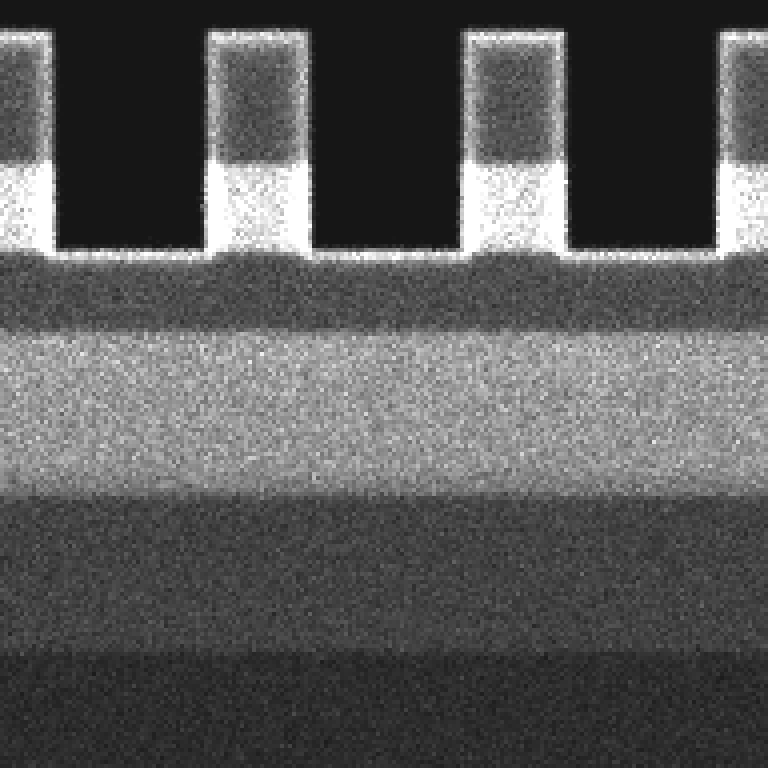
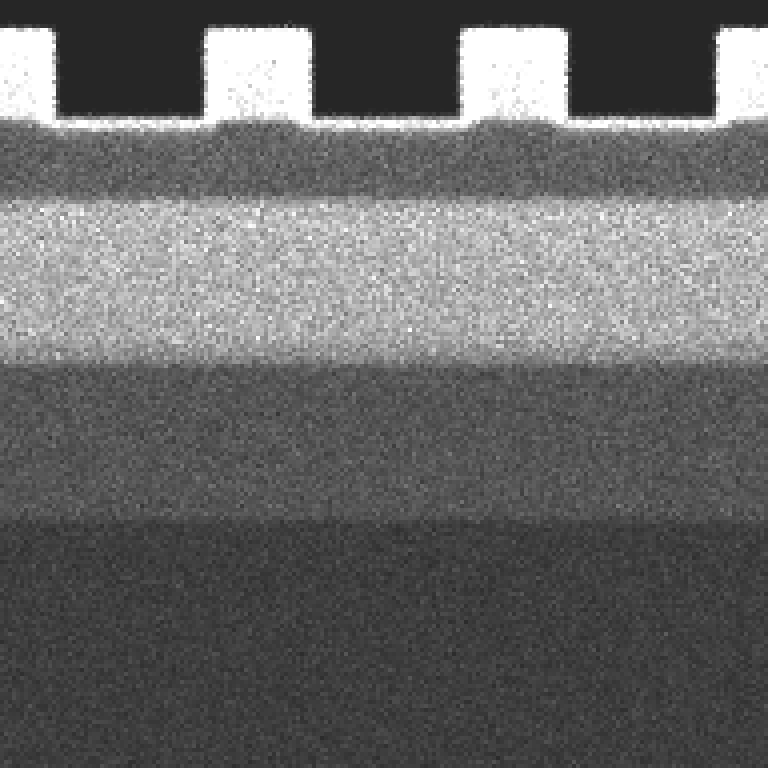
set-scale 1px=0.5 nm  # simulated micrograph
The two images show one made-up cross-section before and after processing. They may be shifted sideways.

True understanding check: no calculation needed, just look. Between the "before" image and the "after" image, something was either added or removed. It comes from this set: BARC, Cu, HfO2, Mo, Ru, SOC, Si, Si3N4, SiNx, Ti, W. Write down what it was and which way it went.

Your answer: SOC (removed)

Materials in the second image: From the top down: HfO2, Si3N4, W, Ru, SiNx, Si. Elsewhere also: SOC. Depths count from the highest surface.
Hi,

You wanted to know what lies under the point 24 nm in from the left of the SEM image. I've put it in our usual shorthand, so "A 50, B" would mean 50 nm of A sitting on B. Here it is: HfO2 44, Si3N4 40, W 72, Ru 10, SiNx 78, Si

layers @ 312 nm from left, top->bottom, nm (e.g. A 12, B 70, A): empty 44, Si3N4 40, W 72, Ru 10, SiNx 78, Si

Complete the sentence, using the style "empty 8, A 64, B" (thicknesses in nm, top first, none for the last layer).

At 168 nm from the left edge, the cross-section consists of empty 44, Si3N4 40, W 72, Ru 10, SiNx 78, Si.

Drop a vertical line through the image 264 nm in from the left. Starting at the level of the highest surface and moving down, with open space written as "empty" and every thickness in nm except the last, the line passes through HfO2 44, Si3N4 40, W 72, Ru 10, SiNx 78, Si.